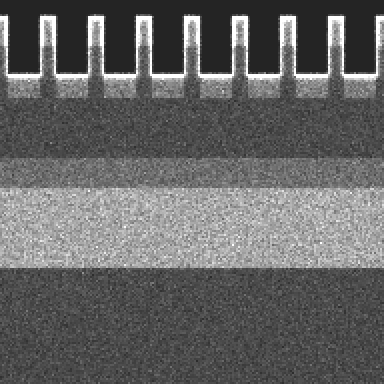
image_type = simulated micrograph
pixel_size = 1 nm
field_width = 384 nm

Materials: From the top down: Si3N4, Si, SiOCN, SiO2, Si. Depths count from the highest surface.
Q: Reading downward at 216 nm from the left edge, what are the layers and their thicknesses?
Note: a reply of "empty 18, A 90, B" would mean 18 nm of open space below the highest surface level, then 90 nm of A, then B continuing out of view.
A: empty 58, Si3N4 24, Si 60, SiOCN 30, SiO2 80, Si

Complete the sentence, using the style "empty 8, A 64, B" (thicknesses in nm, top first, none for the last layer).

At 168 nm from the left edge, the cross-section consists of empty 58, Si3N4 24, Si 60, SiOCN 30, SiO2 80, Si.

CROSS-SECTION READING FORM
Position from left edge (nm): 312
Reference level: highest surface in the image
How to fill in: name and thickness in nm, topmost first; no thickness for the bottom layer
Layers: empty 58, Si3N4 24, Si 60, SiOCN 30, SiO2 80, Si